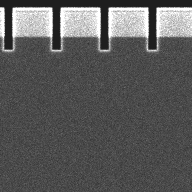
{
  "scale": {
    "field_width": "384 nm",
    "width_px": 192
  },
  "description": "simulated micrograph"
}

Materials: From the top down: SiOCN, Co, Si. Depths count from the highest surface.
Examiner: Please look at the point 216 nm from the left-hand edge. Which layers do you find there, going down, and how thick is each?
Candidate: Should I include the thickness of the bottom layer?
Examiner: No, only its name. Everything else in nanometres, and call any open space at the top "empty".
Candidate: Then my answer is empty 84, Si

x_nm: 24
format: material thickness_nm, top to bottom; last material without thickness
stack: empty 84, Si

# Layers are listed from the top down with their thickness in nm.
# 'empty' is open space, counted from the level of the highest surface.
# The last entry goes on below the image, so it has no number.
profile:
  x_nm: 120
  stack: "empty 84, Si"